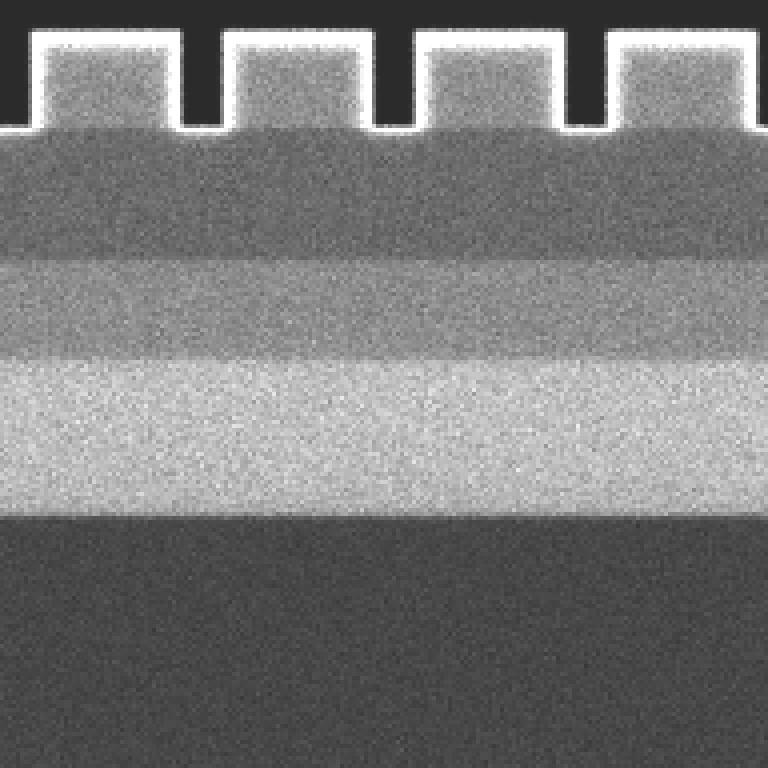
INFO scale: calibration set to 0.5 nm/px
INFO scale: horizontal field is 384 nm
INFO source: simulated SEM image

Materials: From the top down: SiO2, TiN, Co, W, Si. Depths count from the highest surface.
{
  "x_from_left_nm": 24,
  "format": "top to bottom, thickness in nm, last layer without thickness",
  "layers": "SiO2 48, TiN 66, Co 50, W 78, Si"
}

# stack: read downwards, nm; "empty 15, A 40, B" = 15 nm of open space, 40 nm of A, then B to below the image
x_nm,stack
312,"SiO2 48, TiN 66, Co 50, W 78, Si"